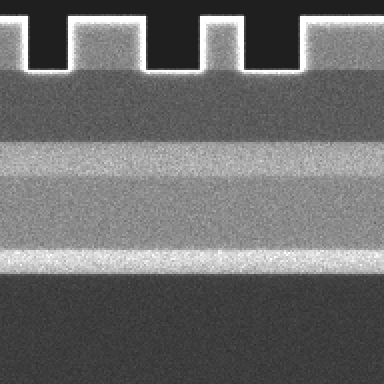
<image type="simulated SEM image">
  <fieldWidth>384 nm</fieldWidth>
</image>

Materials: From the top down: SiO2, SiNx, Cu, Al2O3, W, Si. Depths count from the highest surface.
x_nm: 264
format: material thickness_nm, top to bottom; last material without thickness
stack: empty 54, SiNx 72, Cu 34, Al2O3 74, W 24, Si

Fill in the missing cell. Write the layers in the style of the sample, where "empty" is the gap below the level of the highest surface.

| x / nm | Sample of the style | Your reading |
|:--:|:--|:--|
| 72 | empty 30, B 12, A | SiO2 54, SiNx 72, Cu 34, Al2O3 74, W 24, Si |